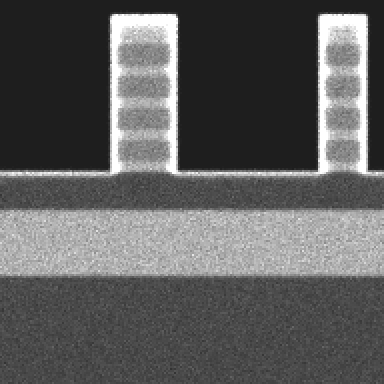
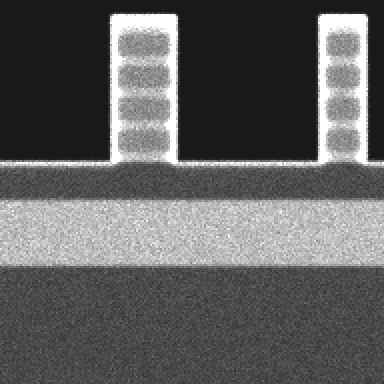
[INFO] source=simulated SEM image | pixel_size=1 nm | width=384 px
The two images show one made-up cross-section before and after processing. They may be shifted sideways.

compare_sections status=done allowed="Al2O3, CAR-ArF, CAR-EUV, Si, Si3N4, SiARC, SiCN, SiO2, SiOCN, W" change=removed material="Al2O3"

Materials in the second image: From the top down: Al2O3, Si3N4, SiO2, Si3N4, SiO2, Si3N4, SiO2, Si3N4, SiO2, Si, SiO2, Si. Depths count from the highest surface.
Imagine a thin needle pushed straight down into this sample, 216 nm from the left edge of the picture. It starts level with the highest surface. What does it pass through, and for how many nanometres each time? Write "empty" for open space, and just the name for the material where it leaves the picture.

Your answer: empty 146, Si 38, SiO2 66, Si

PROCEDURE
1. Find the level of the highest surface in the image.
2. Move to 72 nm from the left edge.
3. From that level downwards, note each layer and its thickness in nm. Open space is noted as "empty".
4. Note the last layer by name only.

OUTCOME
empty 146, Si 38, SiO2 66, Si